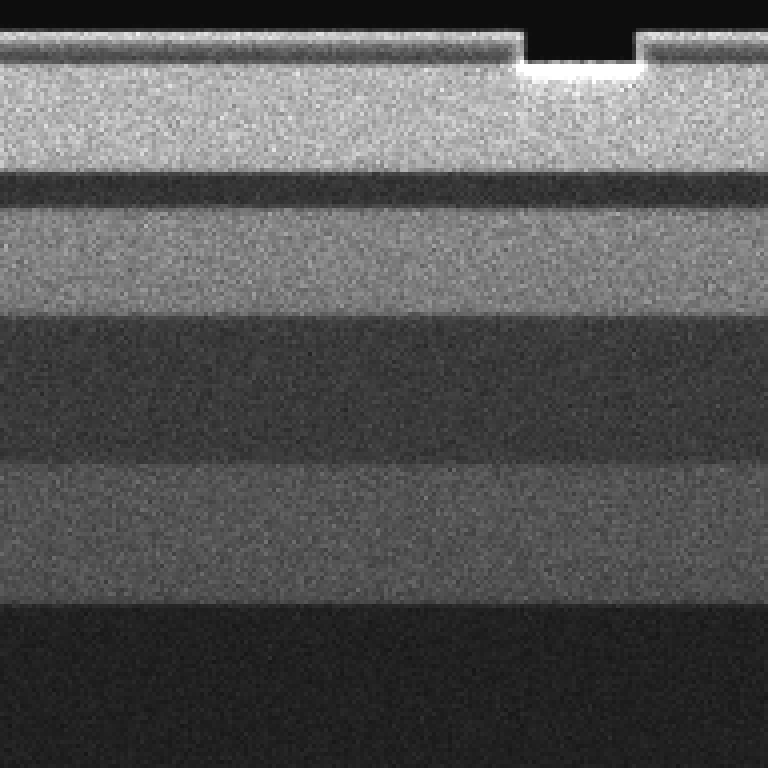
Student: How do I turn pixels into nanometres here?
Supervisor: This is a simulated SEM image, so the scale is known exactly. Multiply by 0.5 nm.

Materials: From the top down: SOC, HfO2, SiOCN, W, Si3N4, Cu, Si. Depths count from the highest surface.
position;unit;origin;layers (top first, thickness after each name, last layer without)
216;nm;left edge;SOC 16, HfO2 54, SiOCN 18, W 54, Si3N4 74, Cu 70, Si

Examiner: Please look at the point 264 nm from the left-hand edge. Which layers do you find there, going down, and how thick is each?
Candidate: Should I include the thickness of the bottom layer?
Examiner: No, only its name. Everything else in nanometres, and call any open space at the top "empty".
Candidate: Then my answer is empty 16, HfO2 54, SiOCN 18, W 54, Si3N4 74, Cu 70, Si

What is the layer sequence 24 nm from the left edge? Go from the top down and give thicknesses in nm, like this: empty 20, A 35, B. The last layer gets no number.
SOC 16, HfO2 54, SiOCN 18, W 54, Si3N4 74, Cu 70, Si